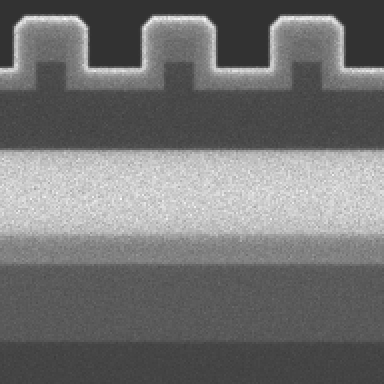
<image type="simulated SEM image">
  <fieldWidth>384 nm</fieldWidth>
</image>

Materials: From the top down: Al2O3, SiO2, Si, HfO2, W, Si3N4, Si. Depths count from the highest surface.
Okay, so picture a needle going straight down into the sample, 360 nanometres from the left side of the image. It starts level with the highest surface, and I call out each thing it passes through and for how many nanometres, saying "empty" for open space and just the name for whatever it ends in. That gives empty 52, Al2O3 22, Si 60, HfO2 84, W 30, Si3N4 78, Si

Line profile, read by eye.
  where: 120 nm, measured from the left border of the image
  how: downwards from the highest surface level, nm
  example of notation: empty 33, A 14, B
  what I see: empty 52, Al2O3 22, Si 60, HfO2 84, W 30, Si3N4 78, Si